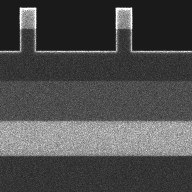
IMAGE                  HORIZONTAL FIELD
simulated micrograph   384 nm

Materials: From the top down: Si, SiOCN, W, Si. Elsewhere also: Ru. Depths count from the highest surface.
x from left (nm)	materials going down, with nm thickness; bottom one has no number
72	empty 86, Si 60, SiOCN 80, W 70, Si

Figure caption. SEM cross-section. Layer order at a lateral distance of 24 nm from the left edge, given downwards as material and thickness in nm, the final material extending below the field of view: empty 86, Si 60, SiOCN 80, W 70, Si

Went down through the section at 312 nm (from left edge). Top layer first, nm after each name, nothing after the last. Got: empty 86, Si 60, SiOCN 80, W 70, Si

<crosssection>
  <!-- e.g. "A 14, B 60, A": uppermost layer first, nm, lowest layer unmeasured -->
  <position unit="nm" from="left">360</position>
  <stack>empty 86, Si 60, SiOCN 80, W 70, Si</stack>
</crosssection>